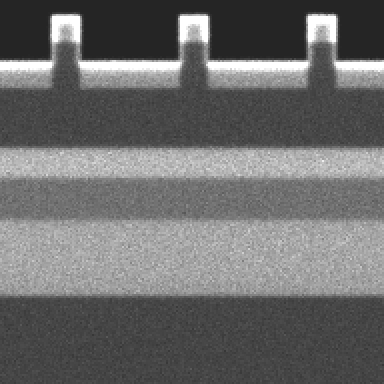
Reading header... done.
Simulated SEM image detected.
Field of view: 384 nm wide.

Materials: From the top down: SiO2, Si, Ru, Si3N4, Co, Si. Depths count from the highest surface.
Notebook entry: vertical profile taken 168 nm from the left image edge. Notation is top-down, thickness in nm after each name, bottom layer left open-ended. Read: empty 46, SiO2 26, Si 60, Ru 30, Si3N4 42, Co 76, Si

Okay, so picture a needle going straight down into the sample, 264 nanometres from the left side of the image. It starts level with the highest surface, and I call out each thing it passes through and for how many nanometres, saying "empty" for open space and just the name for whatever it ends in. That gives empty 46, SiO2 26, Si 60, Ru 30, Si3N4 42, Co 76, Si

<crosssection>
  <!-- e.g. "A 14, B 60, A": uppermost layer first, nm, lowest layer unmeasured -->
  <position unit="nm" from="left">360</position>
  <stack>empty 46, SiO2 26, Si 60, Ru 30, Si3N4 42, Co 76, Si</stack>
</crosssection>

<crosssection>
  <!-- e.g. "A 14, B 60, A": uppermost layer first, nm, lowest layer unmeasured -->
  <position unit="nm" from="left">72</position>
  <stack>SiO2 26, Si 106, Ru 30, Si3N4 42, Co 76, Si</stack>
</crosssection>